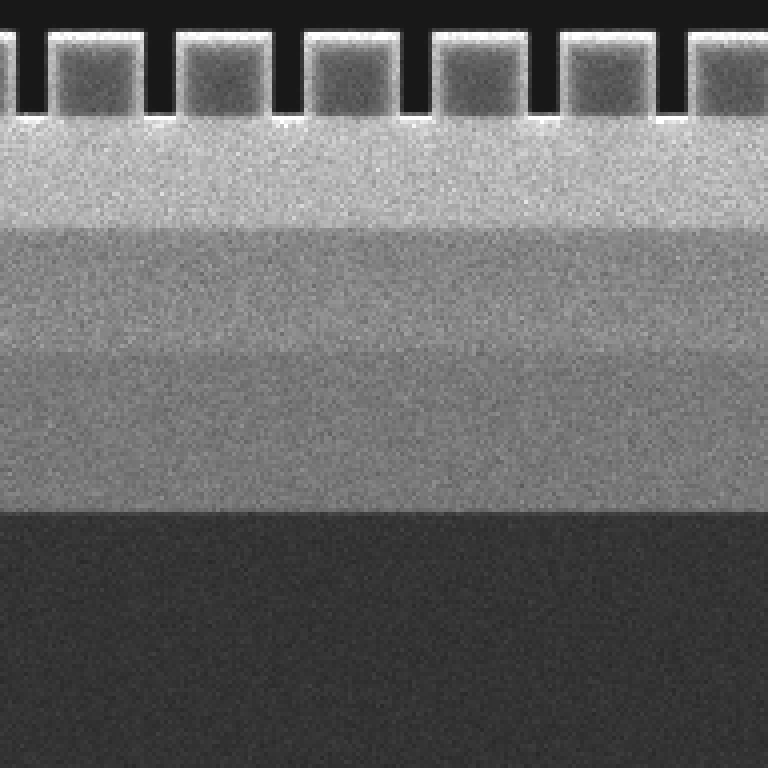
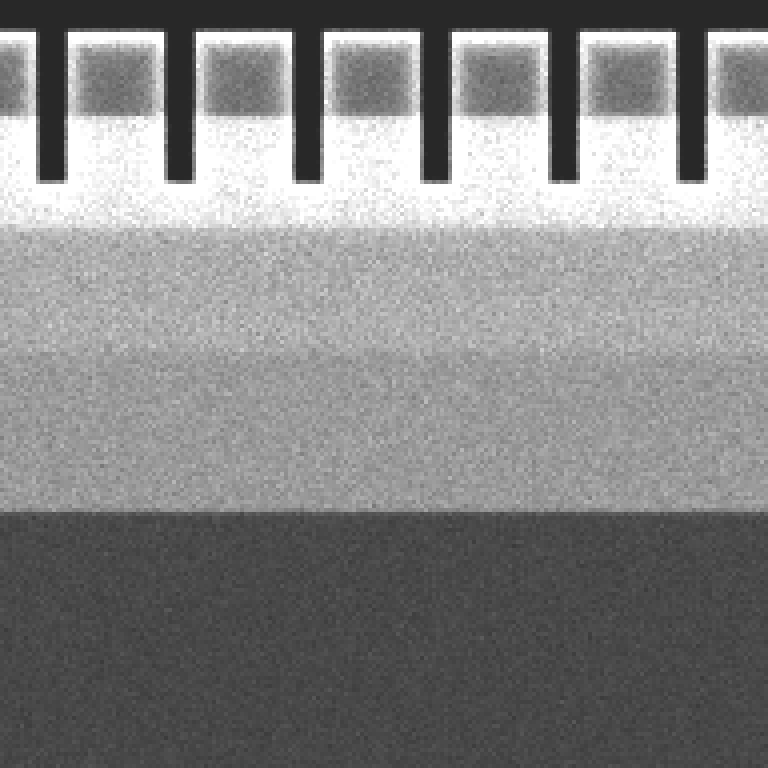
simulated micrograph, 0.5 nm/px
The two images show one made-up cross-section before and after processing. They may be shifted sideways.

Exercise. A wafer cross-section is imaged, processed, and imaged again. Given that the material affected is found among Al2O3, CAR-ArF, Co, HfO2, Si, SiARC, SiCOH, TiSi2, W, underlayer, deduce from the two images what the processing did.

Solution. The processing removed W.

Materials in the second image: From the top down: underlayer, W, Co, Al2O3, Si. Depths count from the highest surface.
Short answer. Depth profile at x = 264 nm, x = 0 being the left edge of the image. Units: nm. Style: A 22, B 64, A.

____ underlayer 42, W 56, Co 62, Al2O3 80, Si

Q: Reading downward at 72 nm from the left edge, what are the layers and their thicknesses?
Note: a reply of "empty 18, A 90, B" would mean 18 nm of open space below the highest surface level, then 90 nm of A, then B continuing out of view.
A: underlayer 42, W 56, Co 62, Al2O3 80, Si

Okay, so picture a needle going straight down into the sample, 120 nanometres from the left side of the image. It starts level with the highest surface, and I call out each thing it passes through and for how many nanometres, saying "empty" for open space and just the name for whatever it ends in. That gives underlayer 42, W 56, Co 62, Al2O3 80, Si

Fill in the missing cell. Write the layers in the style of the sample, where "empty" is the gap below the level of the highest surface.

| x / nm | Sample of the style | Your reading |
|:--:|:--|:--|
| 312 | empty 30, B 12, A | underlayer 42, W 56, Co 62, Al2O3 80, Si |